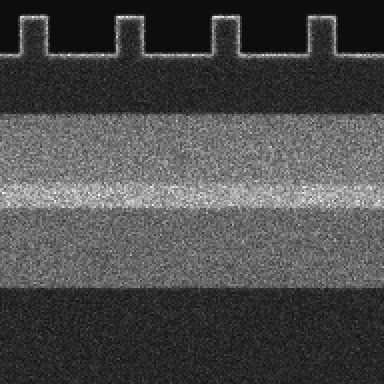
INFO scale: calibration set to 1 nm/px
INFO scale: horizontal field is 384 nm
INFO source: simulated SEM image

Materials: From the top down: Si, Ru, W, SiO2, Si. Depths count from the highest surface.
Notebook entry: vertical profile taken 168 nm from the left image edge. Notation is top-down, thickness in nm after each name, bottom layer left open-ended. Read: empty 38, Si 60, Ru 70, W 24, SiO2 80, Si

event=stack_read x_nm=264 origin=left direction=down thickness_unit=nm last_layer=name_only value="empty 38, Si 60, Ru 70, W 24, SiO2 80, Si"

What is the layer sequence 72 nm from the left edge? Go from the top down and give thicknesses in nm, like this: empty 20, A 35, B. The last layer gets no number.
empty 38, Si 60, Ru 70, W 24, SiO2 80, Si